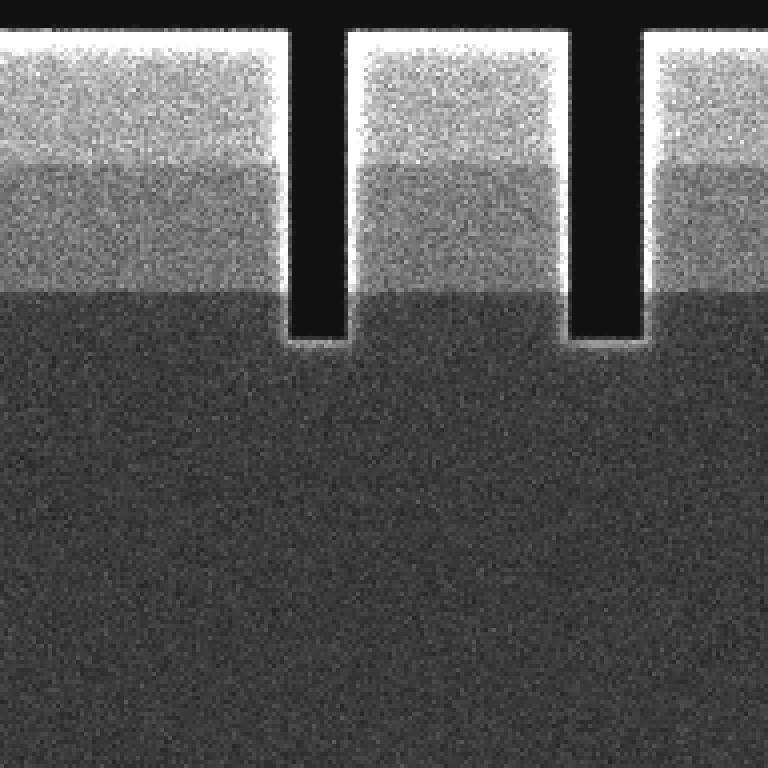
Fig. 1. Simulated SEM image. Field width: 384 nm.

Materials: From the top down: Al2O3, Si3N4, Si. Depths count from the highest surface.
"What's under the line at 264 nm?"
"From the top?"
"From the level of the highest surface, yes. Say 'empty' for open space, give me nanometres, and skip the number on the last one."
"Al2O3 66, Si3N4 64, Si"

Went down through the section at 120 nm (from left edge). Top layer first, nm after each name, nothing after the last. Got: Al2O3 66, Si3N4 64, Si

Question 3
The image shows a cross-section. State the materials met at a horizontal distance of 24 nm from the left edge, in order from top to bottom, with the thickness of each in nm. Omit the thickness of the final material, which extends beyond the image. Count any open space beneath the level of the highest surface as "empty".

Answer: Al2O3 66, Si3N4 64, Si